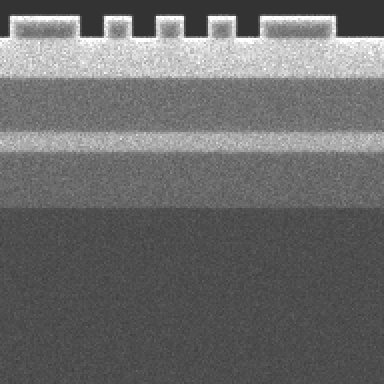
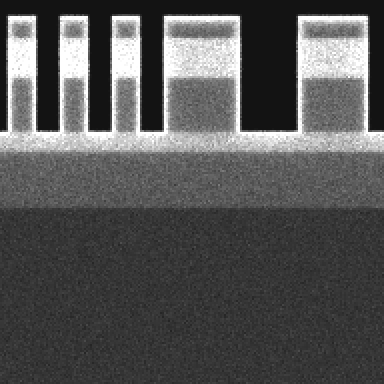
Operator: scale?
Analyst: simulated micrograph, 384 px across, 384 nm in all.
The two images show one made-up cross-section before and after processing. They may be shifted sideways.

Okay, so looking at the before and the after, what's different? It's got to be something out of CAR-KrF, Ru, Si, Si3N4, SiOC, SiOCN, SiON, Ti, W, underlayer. Si3N4 and W, removed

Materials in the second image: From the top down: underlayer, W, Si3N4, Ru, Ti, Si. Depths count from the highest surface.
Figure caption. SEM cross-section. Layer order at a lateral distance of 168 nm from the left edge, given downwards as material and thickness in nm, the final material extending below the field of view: underlayer 22, W 40, Si3N4 54, Ru 20, Ti 56, Si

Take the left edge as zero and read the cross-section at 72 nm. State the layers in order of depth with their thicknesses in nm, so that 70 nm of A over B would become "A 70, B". underlayer 22, W 40, Si3N4 54, Ru 20, Ti 56, Si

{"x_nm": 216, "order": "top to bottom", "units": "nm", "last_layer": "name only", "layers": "underlayer 22, W 40, Si3N4 54, Ru 20, Ti 56, Si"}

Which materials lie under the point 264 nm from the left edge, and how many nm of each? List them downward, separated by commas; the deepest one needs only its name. empty 116, Ru 20, Ti 56, Si